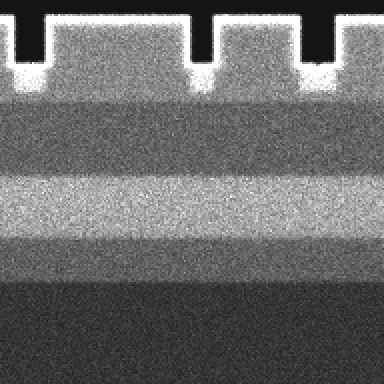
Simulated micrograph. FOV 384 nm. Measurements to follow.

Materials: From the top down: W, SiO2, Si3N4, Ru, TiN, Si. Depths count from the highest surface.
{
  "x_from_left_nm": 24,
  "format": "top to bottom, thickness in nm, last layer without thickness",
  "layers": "empty 48, W 28, SiO2 10, Si3N4 74, Ru 62, TiN 44, Si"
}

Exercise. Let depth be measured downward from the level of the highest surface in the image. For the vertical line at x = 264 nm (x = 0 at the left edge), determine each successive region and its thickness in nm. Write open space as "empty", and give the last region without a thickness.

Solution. SiO2 86, Si3N4 74, Ru 62, TiN 44, Si